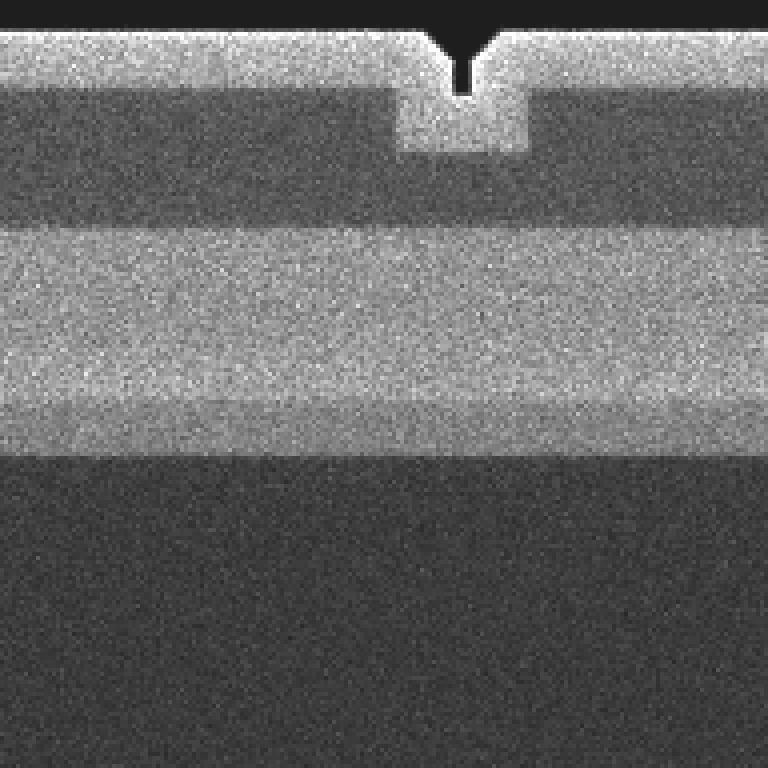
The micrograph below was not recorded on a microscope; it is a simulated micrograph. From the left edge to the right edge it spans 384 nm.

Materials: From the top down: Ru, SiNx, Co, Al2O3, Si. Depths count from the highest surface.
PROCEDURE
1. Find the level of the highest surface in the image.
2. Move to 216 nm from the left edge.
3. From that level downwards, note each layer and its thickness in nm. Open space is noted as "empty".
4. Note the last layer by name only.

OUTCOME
empty 6, Ru 54, SiNx 38, Co 86, Al2O3 28, Si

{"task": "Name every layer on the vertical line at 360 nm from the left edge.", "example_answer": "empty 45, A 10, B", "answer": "Ru 28, SiNx 70, Co 86, Al2O3 28, Si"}